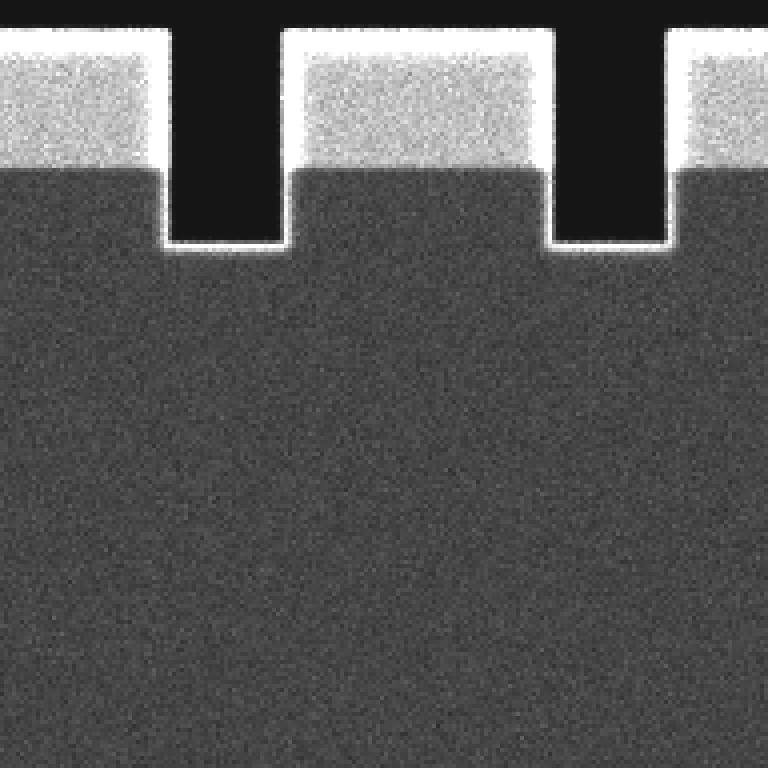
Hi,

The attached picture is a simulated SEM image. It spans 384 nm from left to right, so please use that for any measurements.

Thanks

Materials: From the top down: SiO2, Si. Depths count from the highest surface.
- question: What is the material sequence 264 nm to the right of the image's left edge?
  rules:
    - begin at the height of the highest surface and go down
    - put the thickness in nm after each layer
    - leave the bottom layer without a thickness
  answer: SiO2 68, Si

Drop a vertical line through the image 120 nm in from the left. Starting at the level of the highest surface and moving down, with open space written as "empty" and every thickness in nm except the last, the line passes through empty 106, Si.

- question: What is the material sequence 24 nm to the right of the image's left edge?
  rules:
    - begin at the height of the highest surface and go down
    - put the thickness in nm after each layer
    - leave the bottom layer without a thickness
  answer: SiO2 68, Si